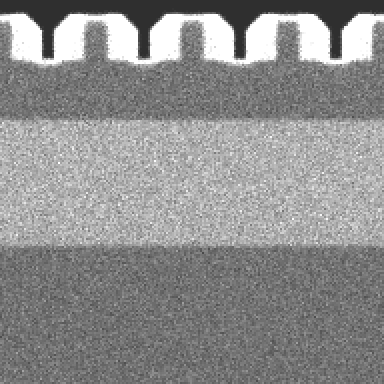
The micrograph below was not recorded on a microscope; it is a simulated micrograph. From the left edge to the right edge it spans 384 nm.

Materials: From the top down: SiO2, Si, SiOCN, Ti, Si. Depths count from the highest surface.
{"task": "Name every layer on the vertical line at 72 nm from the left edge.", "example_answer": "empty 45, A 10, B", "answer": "SiO2 44, Si 60, SiOCN 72, Ti 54, Si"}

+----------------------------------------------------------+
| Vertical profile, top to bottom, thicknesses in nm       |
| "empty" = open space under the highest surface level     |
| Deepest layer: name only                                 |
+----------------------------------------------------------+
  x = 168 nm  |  SiO2 44, Si 60, SiOCN 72, Ti 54, Si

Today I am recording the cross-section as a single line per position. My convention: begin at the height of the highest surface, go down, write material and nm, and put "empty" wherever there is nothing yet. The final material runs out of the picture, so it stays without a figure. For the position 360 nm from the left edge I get SiO2 44, Si 60, SiOCN 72, Ti 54, Si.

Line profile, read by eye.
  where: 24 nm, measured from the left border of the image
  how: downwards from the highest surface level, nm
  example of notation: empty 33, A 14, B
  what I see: SiO2 44, Si 60, SiOCN 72, Ti 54, Si